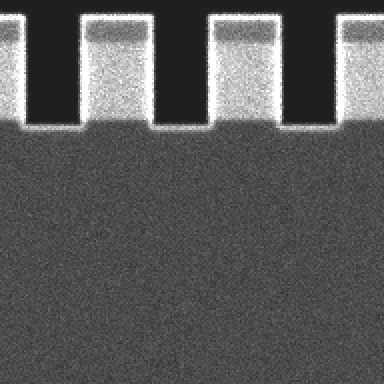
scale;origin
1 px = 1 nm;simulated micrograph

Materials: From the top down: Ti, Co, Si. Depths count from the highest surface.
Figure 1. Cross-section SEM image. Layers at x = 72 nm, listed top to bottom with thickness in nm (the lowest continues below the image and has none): empty 110, Si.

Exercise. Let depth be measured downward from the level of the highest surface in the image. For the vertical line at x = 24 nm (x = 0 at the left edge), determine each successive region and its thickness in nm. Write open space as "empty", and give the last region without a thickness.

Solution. empty 110, Si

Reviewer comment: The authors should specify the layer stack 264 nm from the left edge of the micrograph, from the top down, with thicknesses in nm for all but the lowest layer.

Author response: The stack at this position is Ti 26, Co 78, Si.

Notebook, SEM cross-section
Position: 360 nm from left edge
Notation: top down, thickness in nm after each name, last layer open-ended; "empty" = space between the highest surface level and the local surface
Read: Ti 26, Co 78, Si